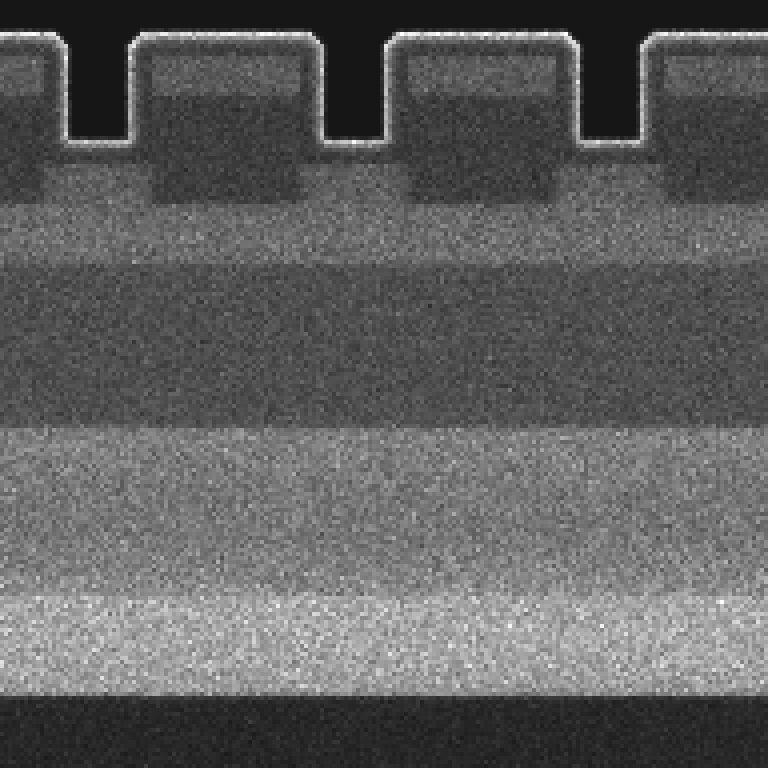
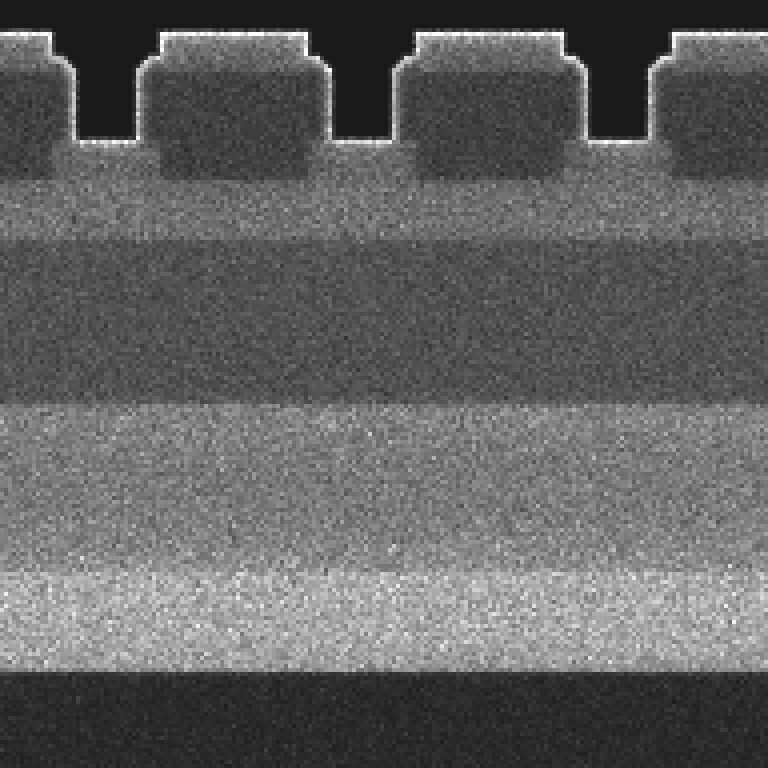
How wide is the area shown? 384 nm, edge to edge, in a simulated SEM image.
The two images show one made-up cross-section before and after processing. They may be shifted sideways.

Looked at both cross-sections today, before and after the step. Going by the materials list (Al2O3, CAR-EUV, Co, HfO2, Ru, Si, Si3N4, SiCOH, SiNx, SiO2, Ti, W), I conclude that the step removed SiNx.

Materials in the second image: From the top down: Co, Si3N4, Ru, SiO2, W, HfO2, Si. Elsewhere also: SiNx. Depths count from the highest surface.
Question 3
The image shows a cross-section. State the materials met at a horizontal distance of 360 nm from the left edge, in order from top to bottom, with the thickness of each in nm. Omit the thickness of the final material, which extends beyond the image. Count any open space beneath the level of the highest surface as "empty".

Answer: Co 20, Si3N4 54, Ru 30, SiO2 82, W 84, HfO2 50, Si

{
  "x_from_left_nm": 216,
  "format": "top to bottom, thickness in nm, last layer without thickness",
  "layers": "Co 20, Si3N4 54, Ru 30, SiO2 82, W 84, HfO2 50, Si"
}